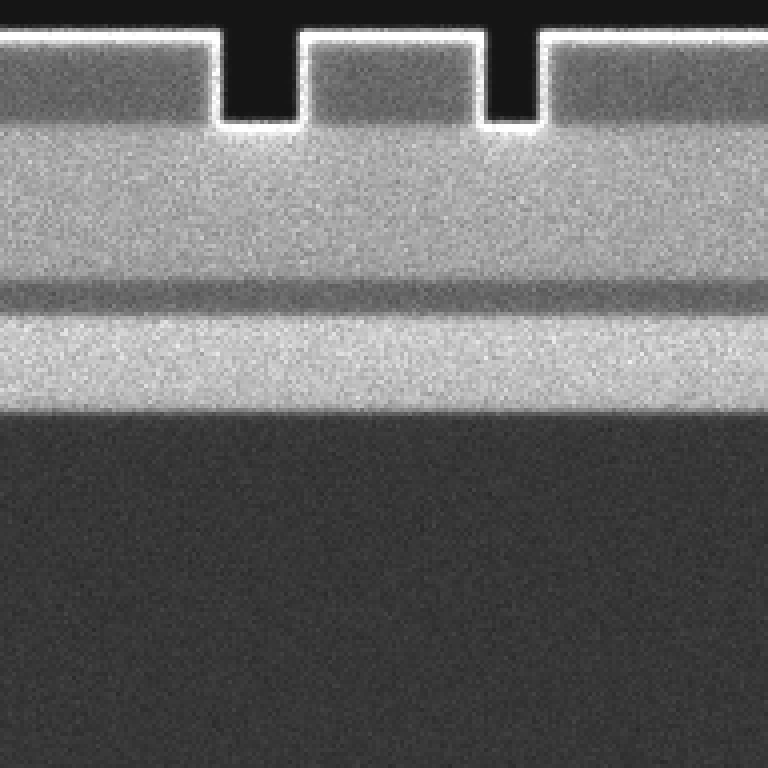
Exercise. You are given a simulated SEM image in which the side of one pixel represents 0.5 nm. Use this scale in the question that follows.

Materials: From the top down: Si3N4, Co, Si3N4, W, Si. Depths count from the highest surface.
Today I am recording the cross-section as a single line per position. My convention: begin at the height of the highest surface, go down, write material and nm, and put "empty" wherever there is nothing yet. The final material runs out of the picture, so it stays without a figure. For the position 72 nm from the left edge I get Si3N4 46, Co 78, Si3N4 18, W 48, Si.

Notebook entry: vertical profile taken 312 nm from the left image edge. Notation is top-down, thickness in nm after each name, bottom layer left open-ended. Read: Si3N4 46, Co 78, Si3N4 18, W 48, Si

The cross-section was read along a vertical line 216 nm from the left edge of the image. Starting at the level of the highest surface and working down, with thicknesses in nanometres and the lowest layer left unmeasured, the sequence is Si3N4 46, Co 78, Si3N4 18, W 48, Si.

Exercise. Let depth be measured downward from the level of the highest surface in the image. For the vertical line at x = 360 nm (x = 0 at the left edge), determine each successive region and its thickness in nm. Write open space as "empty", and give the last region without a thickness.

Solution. Si3N4 46, Co 78, Si3N4 18, W 48, Si